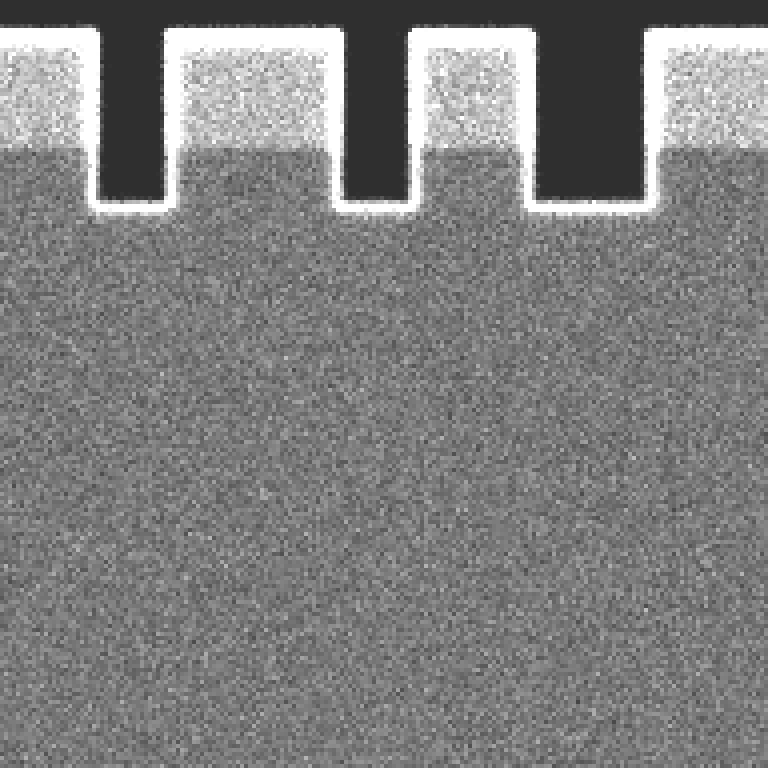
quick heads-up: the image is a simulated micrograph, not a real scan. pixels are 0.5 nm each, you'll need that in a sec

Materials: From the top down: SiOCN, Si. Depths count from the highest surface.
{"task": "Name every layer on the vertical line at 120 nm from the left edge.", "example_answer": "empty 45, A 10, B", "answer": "SiOCN 58, Si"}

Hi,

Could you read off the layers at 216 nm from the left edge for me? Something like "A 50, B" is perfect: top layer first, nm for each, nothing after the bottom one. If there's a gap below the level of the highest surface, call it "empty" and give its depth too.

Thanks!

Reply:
SiOCN 58, Si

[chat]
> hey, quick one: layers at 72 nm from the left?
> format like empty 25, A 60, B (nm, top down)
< empty 86, Si